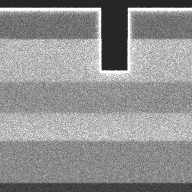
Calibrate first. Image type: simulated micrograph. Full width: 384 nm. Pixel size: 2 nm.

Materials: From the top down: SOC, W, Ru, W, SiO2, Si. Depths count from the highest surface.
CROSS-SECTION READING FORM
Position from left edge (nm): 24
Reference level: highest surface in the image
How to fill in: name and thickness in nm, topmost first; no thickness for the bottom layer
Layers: SOC 62, W 86, Ru 62, W 56, SiO2 84, Si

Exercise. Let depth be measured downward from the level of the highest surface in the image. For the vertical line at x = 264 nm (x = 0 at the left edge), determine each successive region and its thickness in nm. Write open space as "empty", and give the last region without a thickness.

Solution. SOC 62, W 86, Ru 62, W 56, SiO2 84, Si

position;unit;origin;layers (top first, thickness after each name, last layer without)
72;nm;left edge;SOC 62, W 86, Ru 62, W 56, SiO2 84, Si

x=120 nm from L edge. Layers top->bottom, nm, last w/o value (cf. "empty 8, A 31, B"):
SOC 62, W 86, Ru 62, W 56, SiO2 84, Si